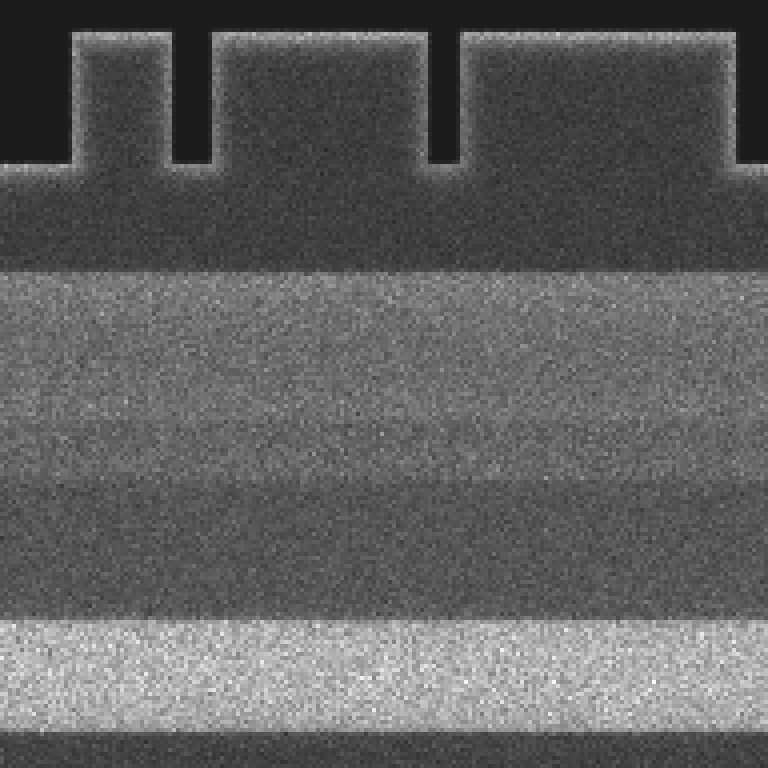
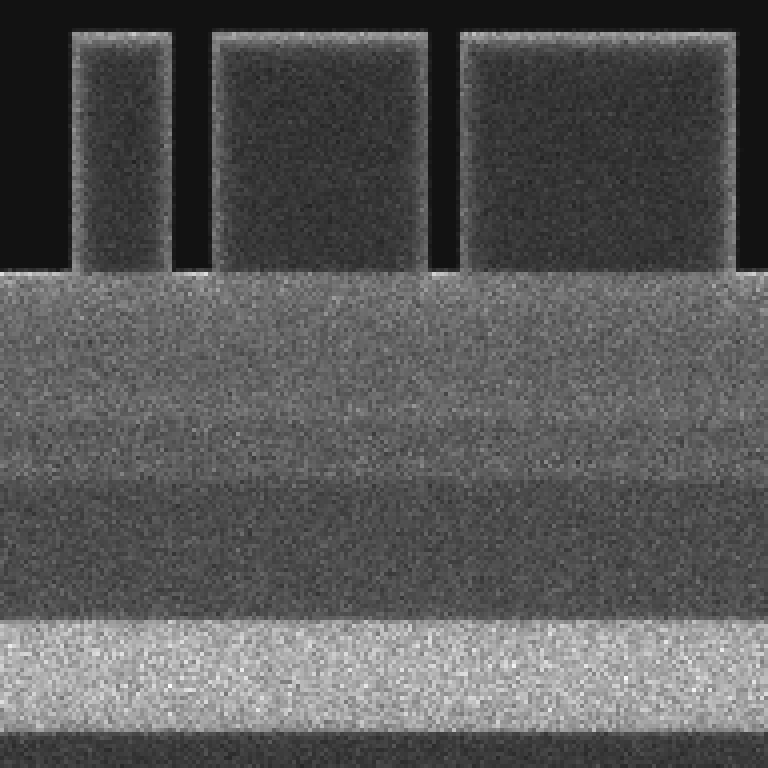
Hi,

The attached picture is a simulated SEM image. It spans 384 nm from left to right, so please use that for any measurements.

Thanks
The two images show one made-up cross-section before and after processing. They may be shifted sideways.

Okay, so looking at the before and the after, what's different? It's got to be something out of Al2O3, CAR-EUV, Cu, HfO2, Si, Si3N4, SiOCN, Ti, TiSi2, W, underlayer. underlayer, removed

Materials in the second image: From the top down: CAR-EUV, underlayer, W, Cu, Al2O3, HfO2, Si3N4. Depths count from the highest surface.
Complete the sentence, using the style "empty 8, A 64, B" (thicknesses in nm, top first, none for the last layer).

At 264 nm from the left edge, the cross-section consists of CAR-EUV 66, underlayer 54, W 74, Cu 30, Al2O3 70, HfO2 56, Si3N4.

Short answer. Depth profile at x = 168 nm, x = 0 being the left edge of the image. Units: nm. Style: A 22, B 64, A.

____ CAR-EUV 66, underlayer 54, W 74, Cu 30, Al2O3 70, HfO2 56, Si3N4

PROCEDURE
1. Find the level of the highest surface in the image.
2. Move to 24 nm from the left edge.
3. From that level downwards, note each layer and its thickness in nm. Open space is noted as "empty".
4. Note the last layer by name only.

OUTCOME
empty 120, W 74, Cu 30, Al2O3 70, HfO2 56, Si3N4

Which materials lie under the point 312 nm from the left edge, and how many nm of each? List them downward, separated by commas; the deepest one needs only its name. CAR-EUV 66, underlayer 54, W 74, Cu 30, Al2O3 70, HfO2 56, Si3N4